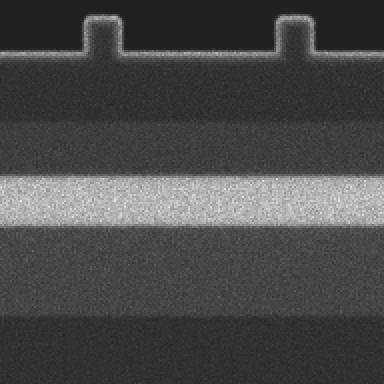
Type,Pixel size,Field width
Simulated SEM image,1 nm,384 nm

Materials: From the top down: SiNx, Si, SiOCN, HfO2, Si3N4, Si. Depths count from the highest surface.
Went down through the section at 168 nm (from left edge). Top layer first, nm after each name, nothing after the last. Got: empty 36, SiNx 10, Si 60, SiOCN 54, HfO2 50, Si3N4 90, Si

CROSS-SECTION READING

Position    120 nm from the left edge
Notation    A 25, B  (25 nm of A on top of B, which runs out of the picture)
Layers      empty 4, SiNx 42, Si 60, SiOCN 54, HfO2 50, Si3N4 90, Si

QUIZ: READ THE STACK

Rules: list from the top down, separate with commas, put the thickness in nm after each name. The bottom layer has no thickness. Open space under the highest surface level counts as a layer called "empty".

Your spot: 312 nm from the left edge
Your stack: empty 4, SiNx 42, Si 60, SiOCN 54, HfO2 50, Si3N4 90, Si